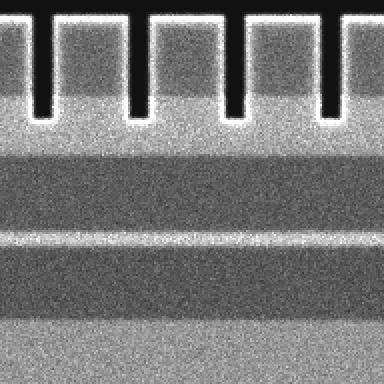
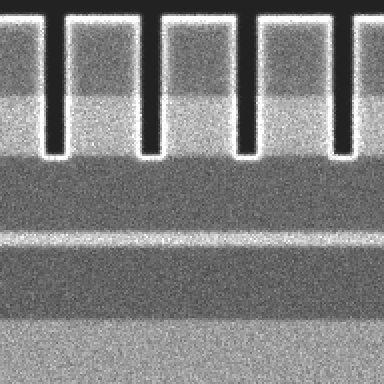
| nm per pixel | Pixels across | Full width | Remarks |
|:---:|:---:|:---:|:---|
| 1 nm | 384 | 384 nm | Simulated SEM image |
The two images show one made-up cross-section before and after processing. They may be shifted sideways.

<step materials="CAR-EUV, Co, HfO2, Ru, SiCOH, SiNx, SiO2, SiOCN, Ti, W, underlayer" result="removed Ru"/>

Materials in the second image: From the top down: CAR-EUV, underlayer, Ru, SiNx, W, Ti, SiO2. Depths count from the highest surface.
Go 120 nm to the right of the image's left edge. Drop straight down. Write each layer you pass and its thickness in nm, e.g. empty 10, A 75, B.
CAR-EUV 60, underlayer 20, Ru 60, SiNx 76, W 14, Ti 74, SiO2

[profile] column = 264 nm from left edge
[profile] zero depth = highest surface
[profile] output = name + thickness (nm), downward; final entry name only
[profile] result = CAR-EUV 60, underlayer 20, Ru 60, SiNx 76, W 14, Ti 74, SiO2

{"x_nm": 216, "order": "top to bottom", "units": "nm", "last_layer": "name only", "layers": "CAR-EUV 60, underlayer 20, Ru 60, SiNx 76, W 14, Ti 74, SiO2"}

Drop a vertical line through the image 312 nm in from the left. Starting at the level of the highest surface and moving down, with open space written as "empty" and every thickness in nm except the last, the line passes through CAR-EUV 60, underlayer 20, Ru 60, SiNx 76, W 14, Ti 74, SiO2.